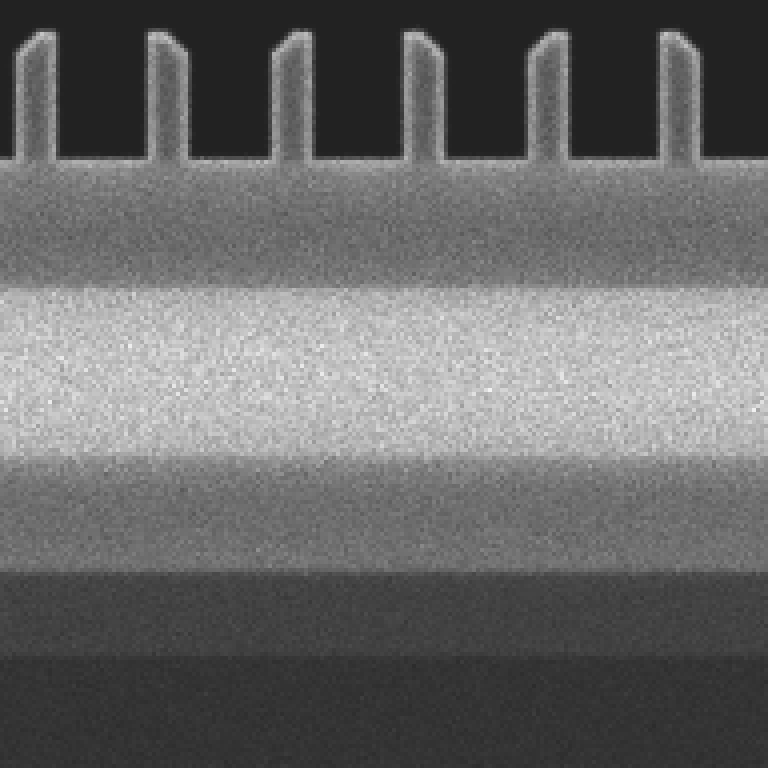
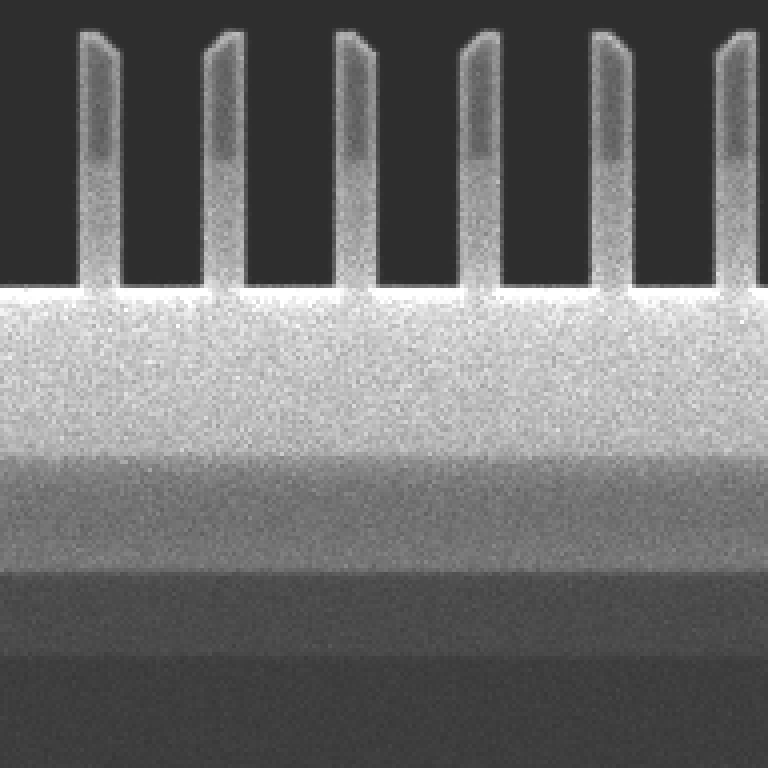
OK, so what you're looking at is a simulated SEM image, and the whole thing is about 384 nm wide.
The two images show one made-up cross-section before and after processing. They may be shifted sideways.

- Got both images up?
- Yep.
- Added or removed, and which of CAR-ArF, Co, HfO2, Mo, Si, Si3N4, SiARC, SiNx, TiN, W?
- removed, Co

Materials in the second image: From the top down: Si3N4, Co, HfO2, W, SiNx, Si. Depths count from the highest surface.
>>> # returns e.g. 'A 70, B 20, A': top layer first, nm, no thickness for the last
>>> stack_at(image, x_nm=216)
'empty 128, HfO2 84, W 58, SiNx 42, Si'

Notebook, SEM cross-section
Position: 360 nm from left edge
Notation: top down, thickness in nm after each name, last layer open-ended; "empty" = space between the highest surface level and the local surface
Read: empty 8, Si3N4 56, Co 64, HfO2 84, W 58, SiNx 42, Si